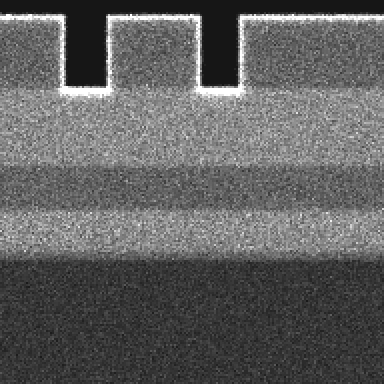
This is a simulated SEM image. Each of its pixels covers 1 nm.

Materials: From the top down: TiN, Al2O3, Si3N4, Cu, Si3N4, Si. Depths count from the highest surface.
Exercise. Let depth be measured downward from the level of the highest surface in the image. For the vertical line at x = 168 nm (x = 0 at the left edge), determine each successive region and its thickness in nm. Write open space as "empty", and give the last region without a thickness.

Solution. TiN 72, Al2O3 78, Si3N4 44, Cu 42, Si3N4 8, Si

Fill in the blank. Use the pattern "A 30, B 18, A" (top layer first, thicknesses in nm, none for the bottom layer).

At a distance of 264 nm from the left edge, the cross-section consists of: TiN 72, Al2O3 78, Si3N4 44, Cu 42, Si3N4 8, Si